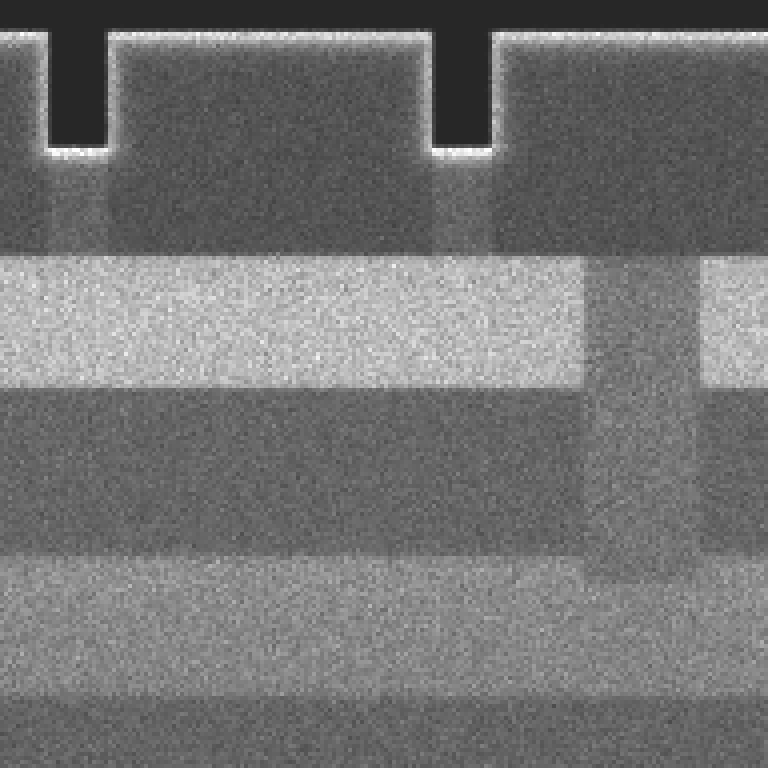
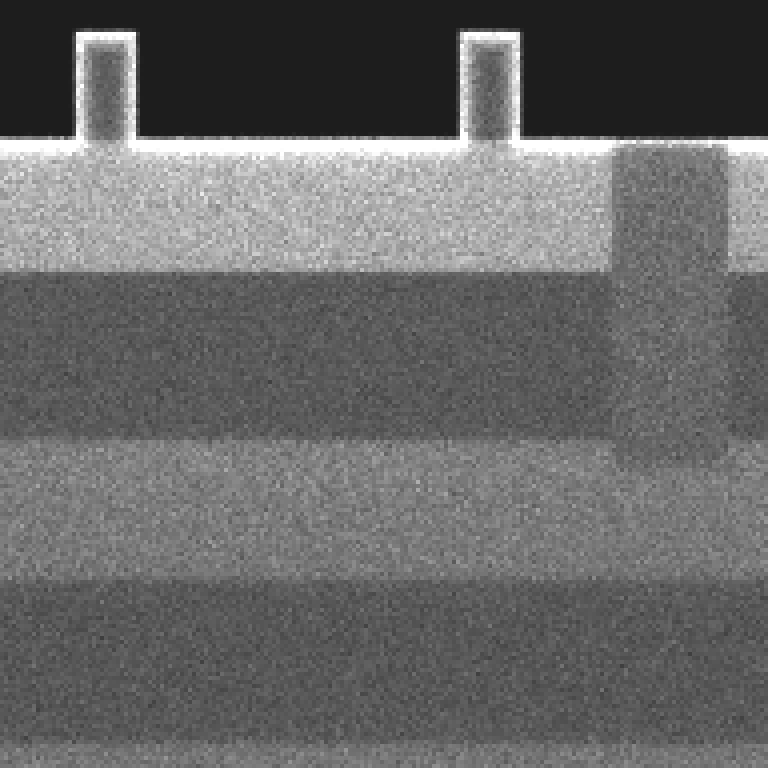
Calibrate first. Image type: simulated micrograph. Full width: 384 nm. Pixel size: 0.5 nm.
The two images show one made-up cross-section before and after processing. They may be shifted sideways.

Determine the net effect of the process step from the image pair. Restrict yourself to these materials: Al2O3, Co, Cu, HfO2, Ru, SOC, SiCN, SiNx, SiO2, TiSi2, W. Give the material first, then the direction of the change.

SOC: removed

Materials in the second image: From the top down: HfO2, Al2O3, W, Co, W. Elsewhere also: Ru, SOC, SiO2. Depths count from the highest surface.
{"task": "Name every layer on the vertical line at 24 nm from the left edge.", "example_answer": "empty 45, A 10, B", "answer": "empty 54, HfO2 66, Al2O3 84, W 70, Co 82, W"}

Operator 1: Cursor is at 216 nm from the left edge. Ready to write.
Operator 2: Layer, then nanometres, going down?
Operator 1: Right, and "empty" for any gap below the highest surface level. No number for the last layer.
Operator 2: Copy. empty 54, HfO2 66, Al2O3 84, W 70, Co 82, W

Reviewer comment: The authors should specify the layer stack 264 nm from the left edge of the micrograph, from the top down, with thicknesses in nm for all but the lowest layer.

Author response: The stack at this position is empty 54, HfO2 66, Al2O3 84, W 70, Co 82, W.